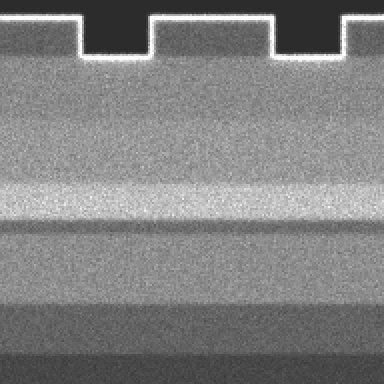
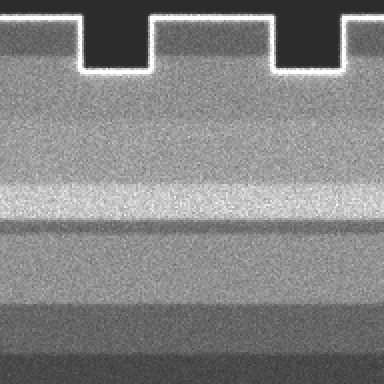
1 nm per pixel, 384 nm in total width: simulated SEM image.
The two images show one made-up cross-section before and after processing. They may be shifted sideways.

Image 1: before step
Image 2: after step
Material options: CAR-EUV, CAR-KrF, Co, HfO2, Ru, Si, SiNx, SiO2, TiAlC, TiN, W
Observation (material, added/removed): Co, removed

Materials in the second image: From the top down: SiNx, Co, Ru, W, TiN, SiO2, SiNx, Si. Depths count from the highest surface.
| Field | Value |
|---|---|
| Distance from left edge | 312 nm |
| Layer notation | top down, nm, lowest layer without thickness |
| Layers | empty 54, Co 50, Ru 64, W 36, TiN 14, SiO2 70, SiNx 50, Si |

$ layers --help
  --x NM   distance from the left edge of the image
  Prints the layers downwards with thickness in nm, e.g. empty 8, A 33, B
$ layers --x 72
SiNx 40, Co 64, Ru 64, W 36, TiN 14, SiO2 70, SiNx 50, Si